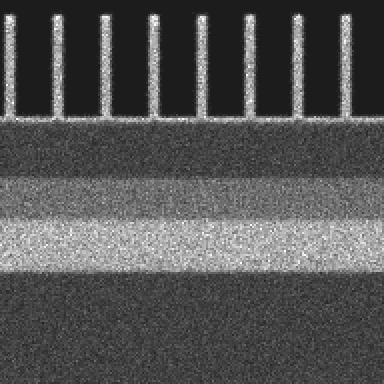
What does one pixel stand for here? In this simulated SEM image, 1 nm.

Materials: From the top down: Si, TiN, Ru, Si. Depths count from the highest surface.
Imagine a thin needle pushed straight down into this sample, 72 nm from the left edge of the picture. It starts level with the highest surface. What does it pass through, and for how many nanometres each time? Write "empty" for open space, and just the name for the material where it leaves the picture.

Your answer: empty 102, Si 60, TiN 42, Ru 52, Si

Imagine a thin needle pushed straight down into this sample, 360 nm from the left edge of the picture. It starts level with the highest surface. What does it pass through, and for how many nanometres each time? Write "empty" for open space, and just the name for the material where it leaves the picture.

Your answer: empty 102, Si 60, TiN 42, Ru 52, Si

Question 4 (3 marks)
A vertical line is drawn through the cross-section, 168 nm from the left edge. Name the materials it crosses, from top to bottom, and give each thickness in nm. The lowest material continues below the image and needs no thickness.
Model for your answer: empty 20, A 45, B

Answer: empty 102, Si 60, TiN 42, Ru 52, Si